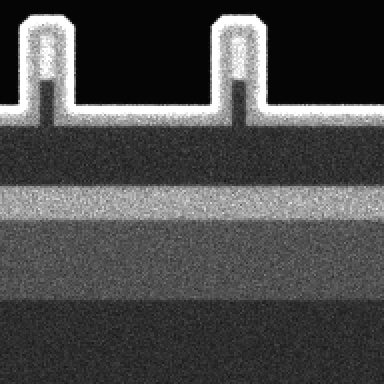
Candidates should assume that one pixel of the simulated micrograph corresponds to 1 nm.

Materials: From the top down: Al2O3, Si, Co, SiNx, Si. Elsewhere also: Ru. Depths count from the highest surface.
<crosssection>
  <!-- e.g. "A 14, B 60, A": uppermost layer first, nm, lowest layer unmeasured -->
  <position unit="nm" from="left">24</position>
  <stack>empty 6, Al2O3 104, Si 60, Co 34, SiNx 80, Si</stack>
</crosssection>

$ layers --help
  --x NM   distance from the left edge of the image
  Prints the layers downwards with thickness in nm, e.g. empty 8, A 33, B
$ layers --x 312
empty 90, Al2O3 20, Si 60, Co 34, SiNx 80, Si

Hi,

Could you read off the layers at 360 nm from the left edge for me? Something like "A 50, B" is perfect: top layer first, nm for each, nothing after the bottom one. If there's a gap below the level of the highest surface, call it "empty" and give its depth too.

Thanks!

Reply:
empty 90, Al2O3 20, Si 60, Co 34, SiNx 80, Si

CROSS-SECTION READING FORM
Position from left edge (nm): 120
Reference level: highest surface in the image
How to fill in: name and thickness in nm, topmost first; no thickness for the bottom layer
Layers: empty 90, Al2O3 20, Si 60, Co 34, SiNx 80, Si